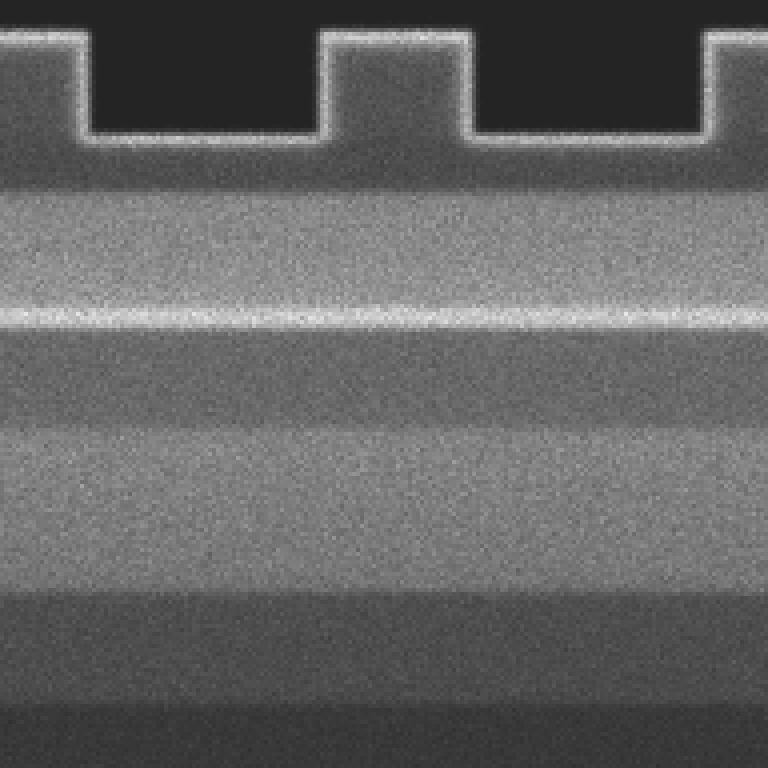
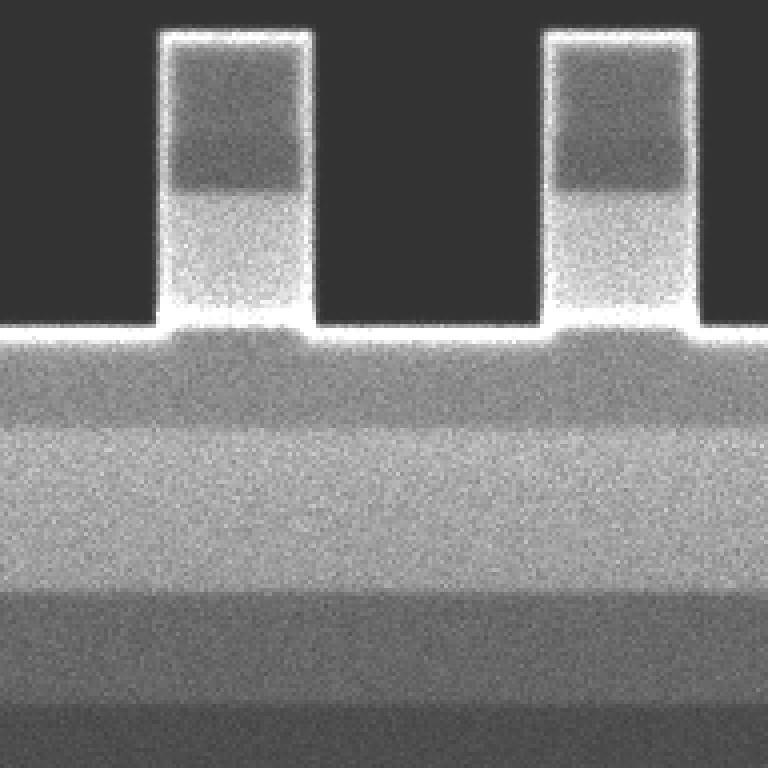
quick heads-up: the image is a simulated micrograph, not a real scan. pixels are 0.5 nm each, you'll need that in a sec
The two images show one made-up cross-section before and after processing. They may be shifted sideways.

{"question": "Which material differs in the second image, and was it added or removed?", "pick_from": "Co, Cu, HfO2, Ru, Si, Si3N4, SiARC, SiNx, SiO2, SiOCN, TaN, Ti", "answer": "HfO2 and Ru and SiNx, removed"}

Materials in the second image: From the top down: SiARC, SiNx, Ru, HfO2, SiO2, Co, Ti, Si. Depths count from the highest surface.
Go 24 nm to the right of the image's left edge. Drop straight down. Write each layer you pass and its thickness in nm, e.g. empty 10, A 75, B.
empty 148, SiO2 50, Co 82, Ti 56, Si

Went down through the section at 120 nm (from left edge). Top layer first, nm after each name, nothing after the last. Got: SiARC 52, SiNx 28, Ru 58, HfO2 10, SiO2 50, Co 82, Ti 56, Si